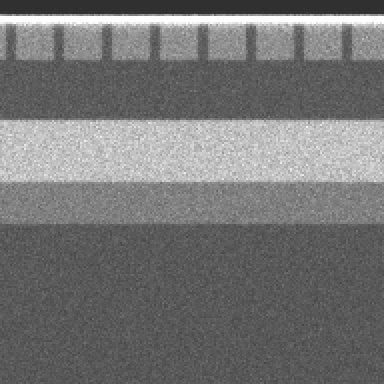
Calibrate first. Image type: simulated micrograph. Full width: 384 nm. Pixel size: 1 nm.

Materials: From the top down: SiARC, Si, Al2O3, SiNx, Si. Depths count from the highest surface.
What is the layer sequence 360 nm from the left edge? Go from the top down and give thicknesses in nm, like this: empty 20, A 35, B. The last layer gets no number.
SiARC 44, Si 60, Al2O3 62, SiNx 42, Si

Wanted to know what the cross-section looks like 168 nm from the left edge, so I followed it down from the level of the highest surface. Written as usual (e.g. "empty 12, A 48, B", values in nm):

SiARC 44, Si 60, Al2O3 62, SiNx 42, Si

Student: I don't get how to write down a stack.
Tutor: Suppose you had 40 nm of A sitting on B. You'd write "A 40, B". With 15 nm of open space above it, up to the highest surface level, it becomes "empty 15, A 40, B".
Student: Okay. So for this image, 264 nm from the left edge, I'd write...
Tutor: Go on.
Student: SiARC 44, Si 60, Al2O3 62, SiNx 42, Si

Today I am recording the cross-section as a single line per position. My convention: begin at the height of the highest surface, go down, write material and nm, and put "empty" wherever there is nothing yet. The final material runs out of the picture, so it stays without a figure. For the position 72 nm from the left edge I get SiARC 44, Si 60, Al2O3 62, SiNx 42, Si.